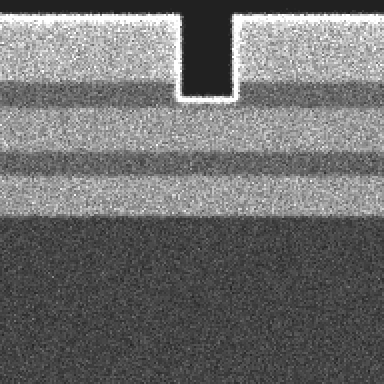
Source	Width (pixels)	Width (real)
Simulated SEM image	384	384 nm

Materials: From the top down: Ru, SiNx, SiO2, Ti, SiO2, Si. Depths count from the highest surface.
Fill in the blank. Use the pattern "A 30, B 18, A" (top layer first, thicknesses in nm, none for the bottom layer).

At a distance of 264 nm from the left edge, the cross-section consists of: Ru 66, SiNx 26, SiO2 44, Ti 24, SiO2 40, Si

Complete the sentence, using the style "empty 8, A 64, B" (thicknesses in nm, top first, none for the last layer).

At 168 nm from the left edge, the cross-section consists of Ru 66, SiNx 26, SiO2 44, Ti 24, SiO2 40, Si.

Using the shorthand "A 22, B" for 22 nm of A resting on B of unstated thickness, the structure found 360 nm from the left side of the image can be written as Ru 66, SiNx 26, SiO2 44, Ti 24, SiO2 40, Si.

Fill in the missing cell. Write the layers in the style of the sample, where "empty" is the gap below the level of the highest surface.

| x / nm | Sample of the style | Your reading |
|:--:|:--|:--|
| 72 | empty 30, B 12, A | Ru 66, SiNx 26, SiO2 44, Ti 24, SiO2 40, Si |